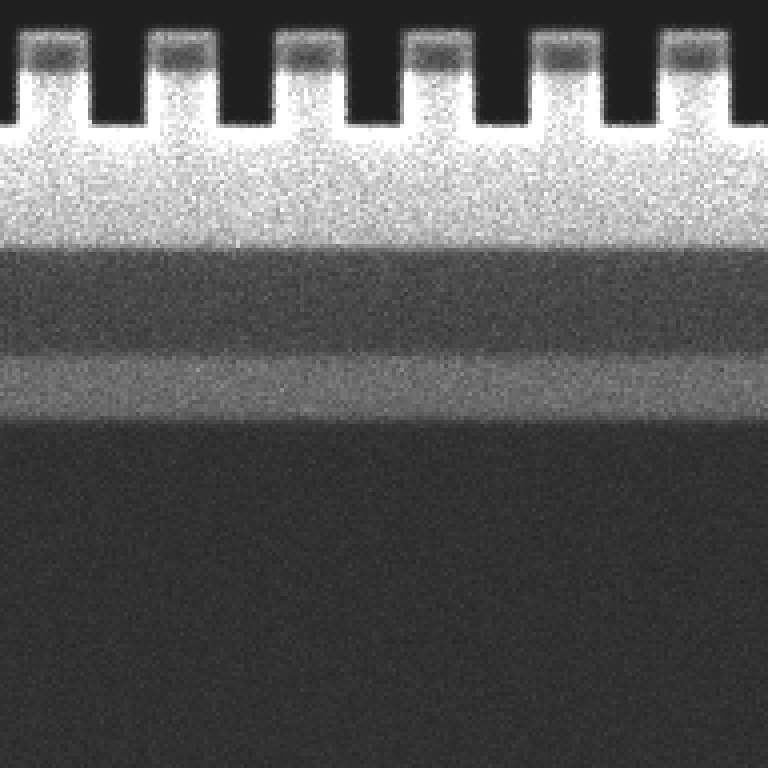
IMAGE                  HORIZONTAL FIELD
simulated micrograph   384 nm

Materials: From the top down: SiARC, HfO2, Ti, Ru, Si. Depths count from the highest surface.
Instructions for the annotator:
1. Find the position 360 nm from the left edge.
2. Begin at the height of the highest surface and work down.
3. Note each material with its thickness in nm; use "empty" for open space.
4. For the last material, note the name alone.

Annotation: SiARC 20, HfO2 88, Ti 54, Ru 32, Si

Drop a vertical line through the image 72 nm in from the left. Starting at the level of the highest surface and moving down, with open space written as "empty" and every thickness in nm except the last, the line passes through empty 48, HfO2 60, Ti 54, Ru 32, Si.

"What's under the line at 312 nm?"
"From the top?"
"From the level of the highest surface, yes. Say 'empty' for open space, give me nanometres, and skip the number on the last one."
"empty 48, HfO2 60, Ti 54, Ru 32, Si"